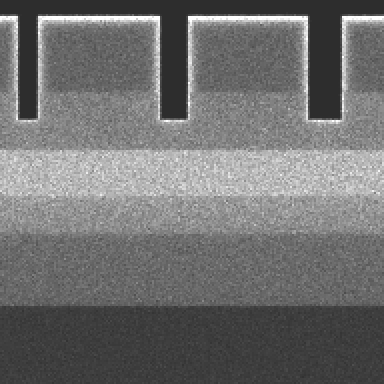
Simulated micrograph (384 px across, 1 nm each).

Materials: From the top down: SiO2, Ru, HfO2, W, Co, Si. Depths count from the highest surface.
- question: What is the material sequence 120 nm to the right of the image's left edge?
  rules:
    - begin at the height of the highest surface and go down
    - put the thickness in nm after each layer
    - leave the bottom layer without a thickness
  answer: SiO2 76, Ru 58, HfO2 46, W 38, Co 72, Si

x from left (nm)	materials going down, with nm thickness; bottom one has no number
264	SiO2 76, Ru 58, HfO2 46, W 38, Co 72, Si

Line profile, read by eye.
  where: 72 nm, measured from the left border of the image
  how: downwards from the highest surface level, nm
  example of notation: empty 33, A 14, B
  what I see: SiO2 76, Ru 58, HfO2 46, W 38, Co 72, Si